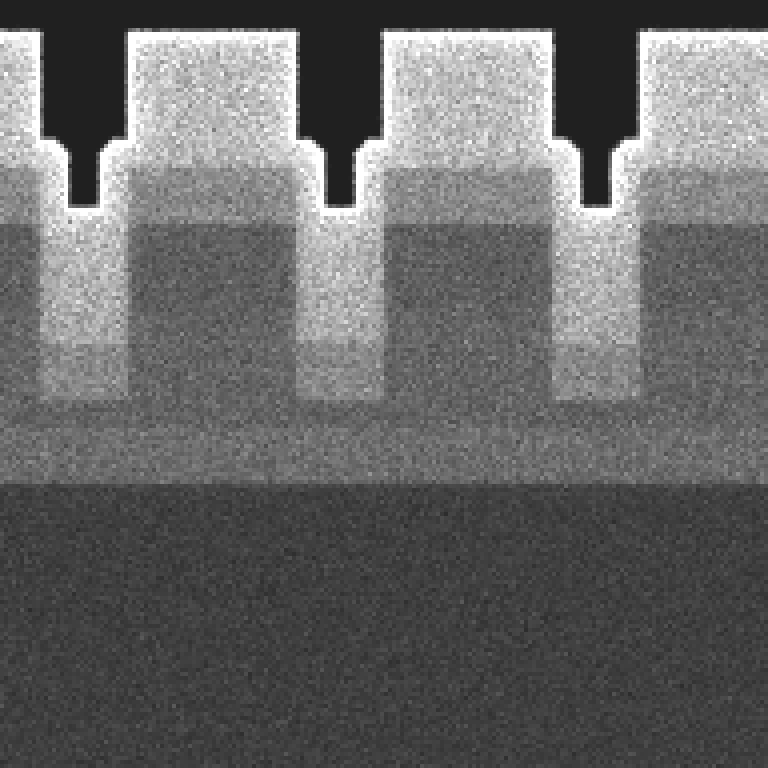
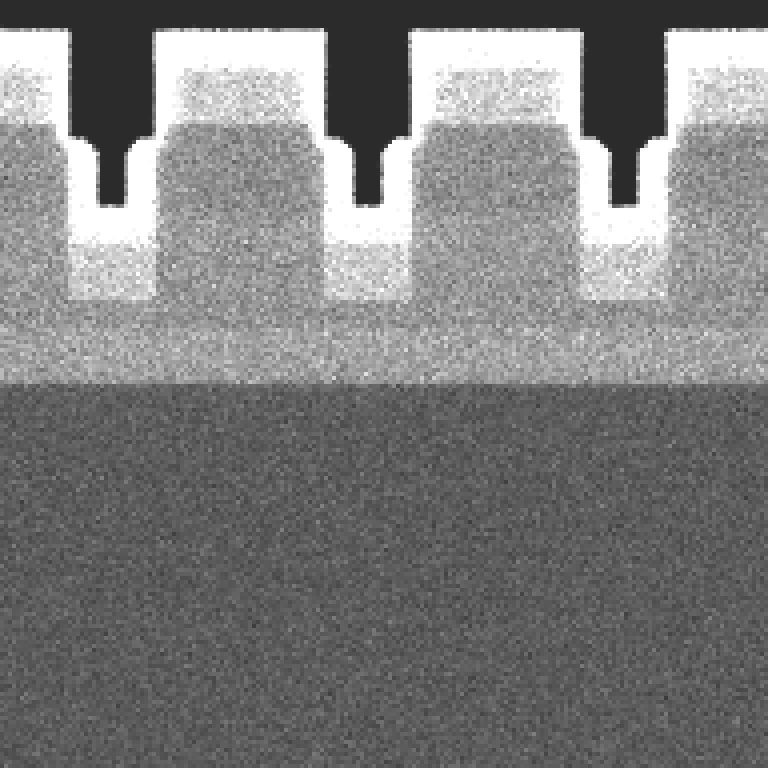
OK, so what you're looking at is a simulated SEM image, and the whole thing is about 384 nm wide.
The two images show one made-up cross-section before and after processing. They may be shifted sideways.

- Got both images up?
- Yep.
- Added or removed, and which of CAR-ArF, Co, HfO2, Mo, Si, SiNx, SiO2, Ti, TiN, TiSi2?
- removed, Co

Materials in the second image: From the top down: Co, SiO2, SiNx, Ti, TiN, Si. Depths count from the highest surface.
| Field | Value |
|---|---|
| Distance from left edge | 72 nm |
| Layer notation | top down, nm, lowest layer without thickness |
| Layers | empty 54, Co 52, SiO2 28, Ti 14, TiN 28, Si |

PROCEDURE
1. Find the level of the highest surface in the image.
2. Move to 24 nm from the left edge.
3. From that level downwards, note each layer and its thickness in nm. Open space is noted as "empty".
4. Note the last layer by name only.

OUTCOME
Co 18, SiO2 28, SiNx 44, Ti 58, TiN 28, Si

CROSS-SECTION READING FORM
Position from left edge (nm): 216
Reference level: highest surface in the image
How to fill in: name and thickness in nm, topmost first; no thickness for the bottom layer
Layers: Co 18, SiO2 28, SiNx 44, Ti 58, TiN 28, Si